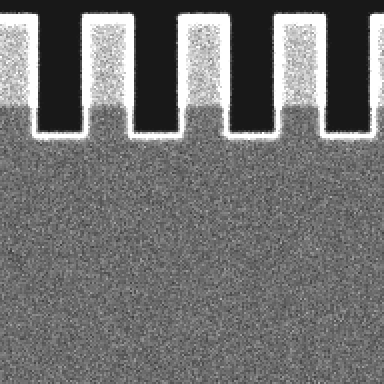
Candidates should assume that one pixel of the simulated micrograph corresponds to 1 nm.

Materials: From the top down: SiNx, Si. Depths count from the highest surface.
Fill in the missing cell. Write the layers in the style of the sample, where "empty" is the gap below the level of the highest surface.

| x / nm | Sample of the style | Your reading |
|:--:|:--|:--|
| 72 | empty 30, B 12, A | empty 118, Si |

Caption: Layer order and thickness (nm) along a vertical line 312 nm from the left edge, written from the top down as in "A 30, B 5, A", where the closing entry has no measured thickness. SiNx 90, Si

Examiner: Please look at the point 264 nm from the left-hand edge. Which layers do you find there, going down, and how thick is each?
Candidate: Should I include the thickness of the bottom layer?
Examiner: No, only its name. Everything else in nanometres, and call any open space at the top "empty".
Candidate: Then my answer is empty 118, Si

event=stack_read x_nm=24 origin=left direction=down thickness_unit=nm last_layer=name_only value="SiNx 90, Si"